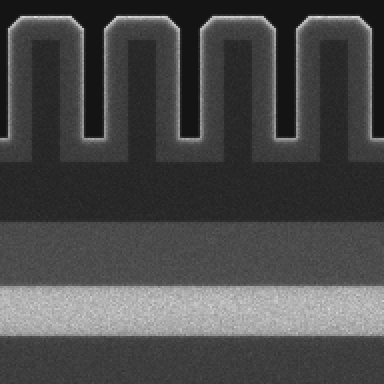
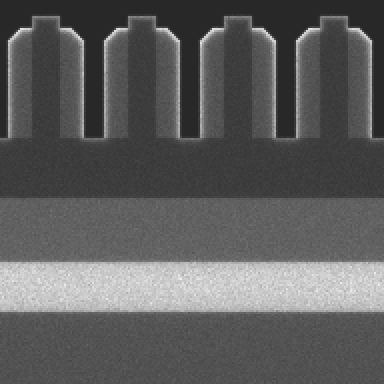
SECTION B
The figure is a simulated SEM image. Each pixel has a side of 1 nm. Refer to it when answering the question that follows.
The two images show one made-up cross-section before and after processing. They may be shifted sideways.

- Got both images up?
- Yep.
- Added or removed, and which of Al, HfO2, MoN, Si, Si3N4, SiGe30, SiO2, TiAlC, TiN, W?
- removed, Si3N4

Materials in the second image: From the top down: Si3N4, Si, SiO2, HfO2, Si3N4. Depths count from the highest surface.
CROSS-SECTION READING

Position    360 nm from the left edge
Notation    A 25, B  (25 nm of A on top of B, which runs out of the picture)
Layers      empty 14, Si3N4 108, Si 60, SiO2 64, HfO2 50, Si3N4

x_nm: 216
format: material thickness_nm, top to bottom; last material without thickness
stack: empty 12, Si3N4 110, Si 60, SiO2 64, HfO2 50, Si3N4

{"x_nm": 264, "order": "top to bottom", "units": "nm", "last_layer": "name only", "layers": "empty 14, Si3N4 108, Si 60, SiO2 64, HfO2 50, Si3N4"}